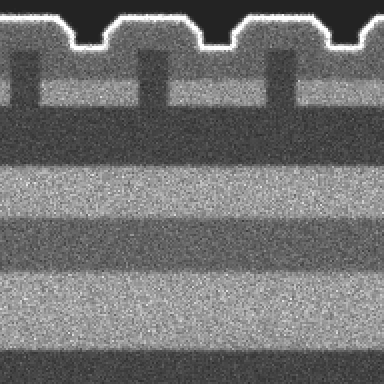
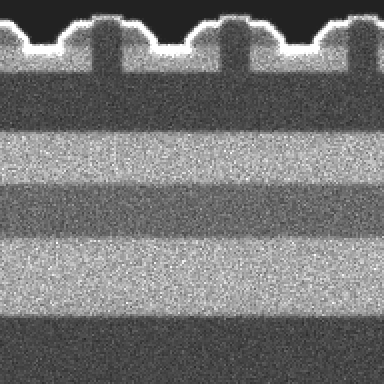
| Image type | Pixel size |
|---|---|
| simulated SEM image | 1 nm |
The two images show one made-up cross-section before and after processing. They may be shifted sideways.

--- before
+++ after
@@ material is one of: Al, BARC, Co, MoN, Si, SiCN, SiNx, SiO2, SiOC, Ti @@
SiNx removed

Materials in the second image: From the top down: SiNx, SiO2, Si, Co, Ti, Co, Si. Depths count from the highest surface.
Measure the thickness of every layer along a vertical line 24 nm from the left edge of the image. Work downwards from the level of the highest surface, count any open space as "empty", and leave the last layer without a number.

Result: empty 20, SiNx 10, SiO2 26, Si 60, Co 52, Ti 54, Co 78, Si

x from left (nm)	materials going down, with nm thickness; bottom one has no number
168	empty 30, SiO2 26, Si 60, Co 52, Ti 54, Co 78, Si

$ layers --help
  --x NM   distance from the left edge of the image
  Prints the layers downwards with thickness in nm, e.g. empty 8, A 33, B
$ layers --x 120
Si 116, Co 52, Ti 54, Co 78, Si